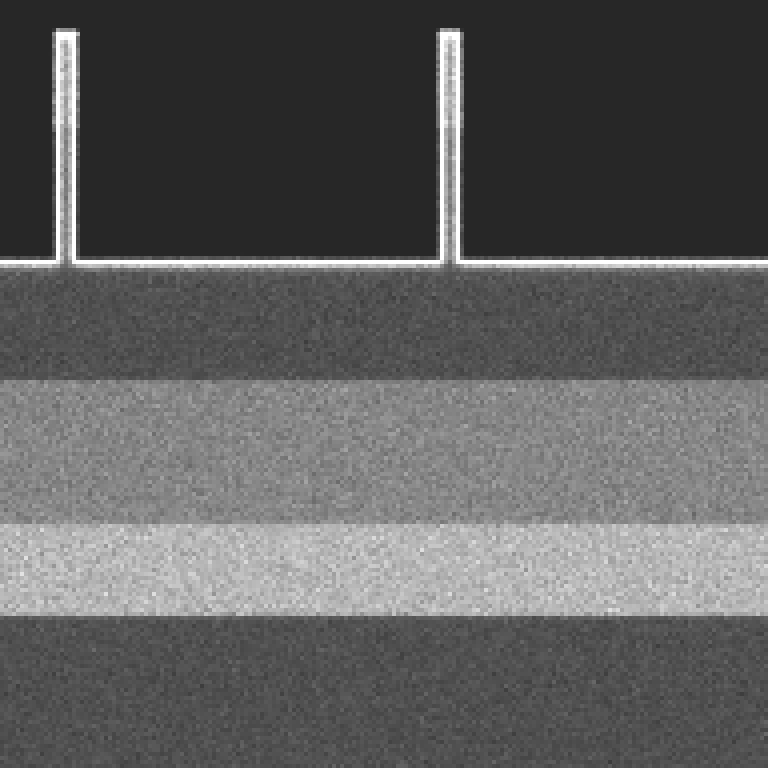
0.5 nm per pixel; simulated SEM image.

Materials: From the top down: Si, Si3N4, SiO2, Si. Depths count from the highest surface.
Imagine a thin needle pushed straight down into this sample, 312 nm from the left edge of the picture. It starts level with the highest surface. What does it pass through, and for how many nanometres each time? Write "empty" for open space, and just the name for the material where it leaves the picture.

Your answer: empty 114, Si 60, Si3N4 72, SiO2 46, Si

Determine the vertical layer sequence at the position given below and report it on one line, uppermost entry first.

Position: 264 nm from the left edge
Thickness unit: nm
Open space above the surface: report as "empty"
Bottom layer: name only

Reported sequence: empty 114, Si 60, Si3N4 72, SiO2 46, Si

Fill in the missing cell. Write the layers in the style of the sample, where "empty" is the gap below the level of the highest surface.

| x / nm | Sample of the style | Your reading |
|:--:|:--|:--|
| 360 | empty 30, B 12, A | empty 114, Si 60, Si3N4 72, SiO2 46, Si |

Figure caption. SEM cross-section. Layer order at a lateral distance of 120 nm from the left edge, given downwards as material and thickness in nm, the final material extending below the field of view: empty 114, Si 60, Si3N4 72, SiO2 46, Si